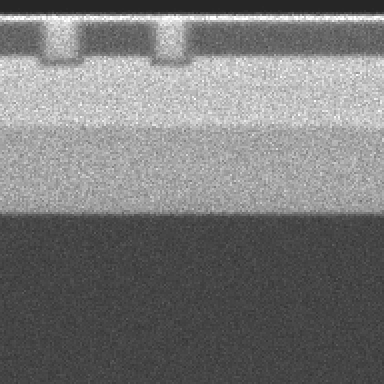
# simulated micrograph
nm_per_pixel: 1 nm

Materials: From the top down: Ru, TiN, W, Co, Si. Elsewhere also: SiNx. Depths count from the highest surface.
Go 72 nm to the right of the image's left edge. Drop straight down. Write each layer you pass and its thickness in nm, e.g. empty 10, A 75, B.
Ru 42, TiN 8, W 60, Co 88, Si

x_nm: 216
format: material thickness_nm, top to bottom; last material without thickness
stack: SiNx 40, W 70, Co 88, Si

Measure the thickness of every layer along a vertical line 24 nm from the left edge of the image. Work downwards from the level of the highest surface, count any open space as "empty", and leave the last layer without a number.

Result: SiNx 40, W 70, Co 88, Si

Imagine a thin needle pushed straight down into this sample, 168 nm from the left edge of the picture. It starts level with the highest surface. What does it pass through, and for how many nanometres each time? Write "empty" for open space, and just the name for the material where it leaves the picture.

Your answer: Ru 42, TiN 8, W 60, Co 88, Si